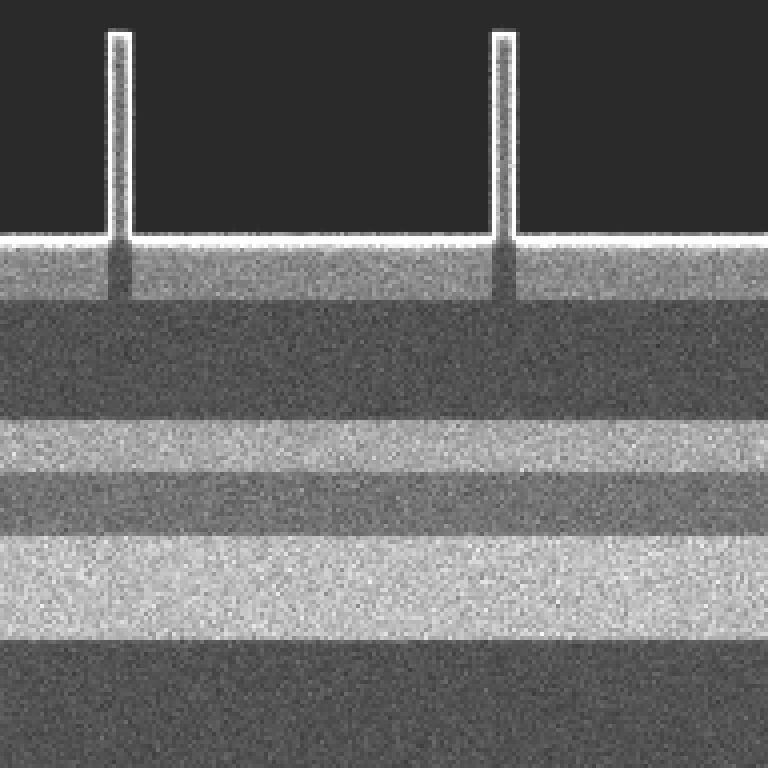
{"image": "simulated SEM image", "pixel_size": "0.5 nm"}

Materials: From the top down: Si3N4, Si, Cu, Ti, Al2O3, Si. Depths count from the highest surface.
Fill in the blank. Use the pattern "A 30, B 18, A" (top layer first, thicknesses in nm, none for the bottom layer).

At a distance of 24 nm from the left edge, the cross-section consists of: empty 102, Si3N4 32, Si 60, Cu 26, Ti 32, Al2O3 52, Si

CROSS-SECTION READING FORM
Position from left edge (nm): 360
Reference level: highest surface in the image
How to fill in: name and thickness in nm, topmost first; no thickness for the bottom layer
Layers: empty 102, Si3N4 32, Si 60, Cu 26, Ti 32, Al2O3 52, Si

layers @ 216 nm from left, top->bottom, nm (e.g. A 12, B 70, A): empty 102, Si3N4 32, Si 60, Cu 26, Ti 32, Al2O3 52, Si